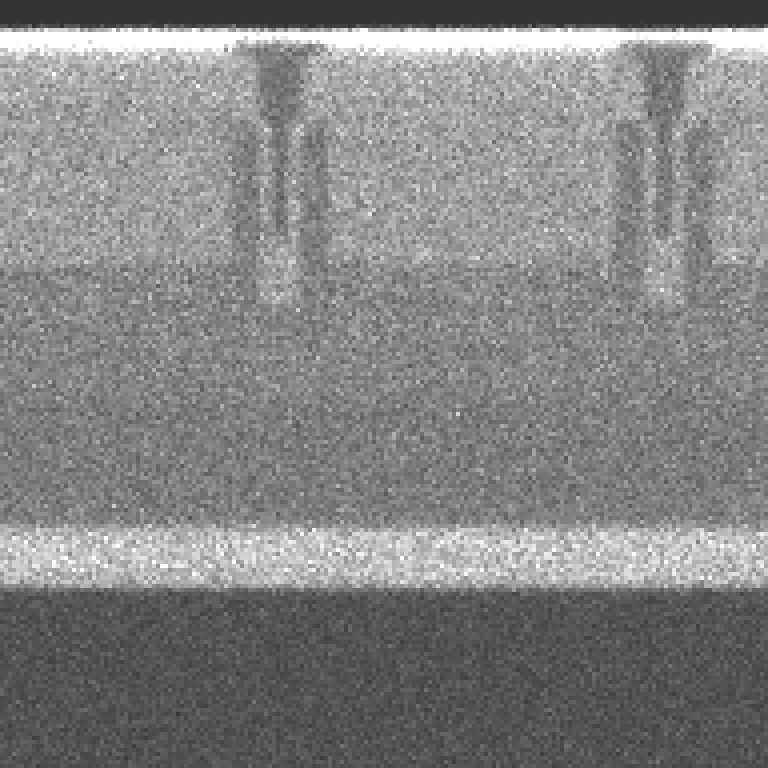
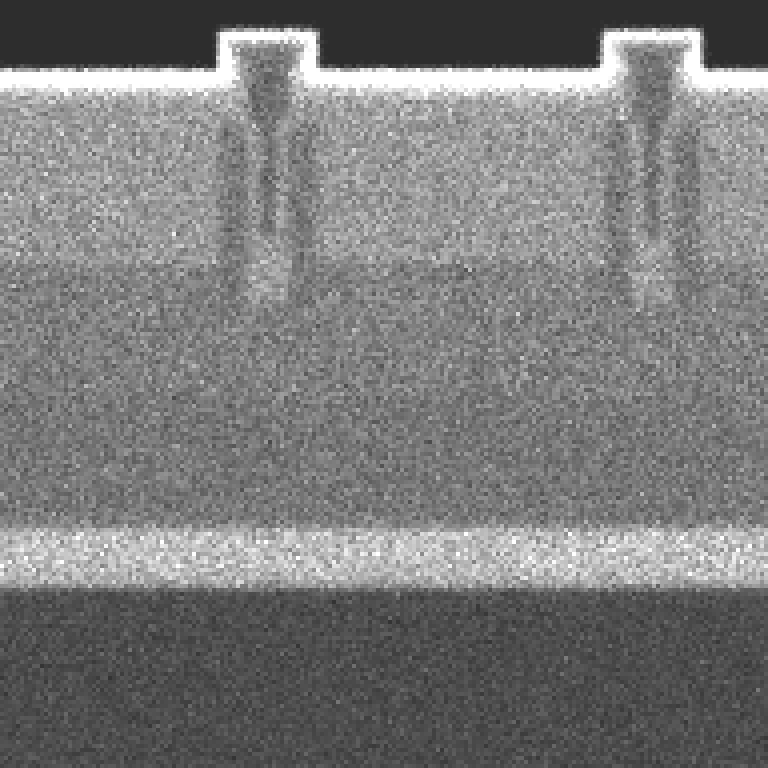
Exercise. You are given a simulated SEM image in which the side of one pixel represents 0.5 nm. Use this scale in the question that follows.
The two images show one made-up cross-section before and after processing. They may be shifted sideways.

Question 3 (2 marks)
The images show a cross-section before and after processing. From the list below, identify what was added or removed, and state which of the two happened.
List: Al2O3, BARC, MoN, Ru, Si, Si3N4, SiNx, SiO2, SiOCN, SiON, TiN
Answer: Al2O3 was removed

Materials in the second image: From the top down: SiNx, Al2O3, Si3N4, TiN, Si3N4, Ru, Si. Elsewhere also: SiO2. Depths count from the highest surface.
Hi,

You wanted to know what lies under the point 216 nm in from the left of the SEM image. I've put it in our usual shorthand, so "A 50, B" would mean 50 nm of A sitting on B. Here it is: empty 20, Al2O3 14, SiO2 82, TiN 68, Si3N4 64, Ru 30, Si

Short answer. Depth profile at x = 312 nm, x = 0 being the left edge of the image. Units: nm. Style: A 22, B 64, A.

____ SiNx 14, Al2O3 34, Si3N4 88, TiN 48, Si3N4 64, Ru 30, Si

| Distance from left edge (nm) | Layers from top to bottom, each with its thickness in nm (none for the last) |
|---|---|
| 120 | SiNx 14, Al2O3 34, Si3N4 88, TiN 48, Si3N4 64, Ru 30, Si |